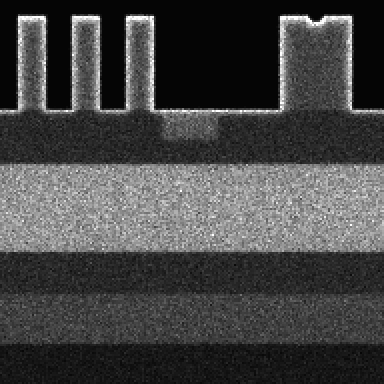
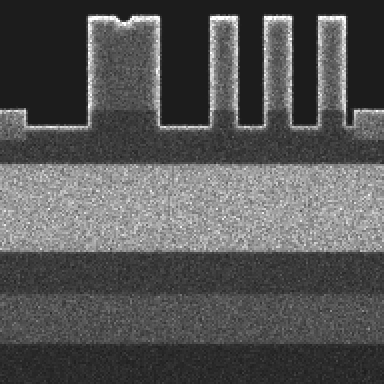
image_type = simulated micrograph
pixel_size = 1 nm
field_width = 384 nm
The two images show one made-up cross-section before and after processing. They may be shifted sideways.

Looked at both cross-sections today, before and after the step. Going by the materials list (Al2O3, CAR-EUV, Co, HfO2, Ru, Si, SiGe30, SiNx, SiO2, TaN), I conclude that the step removed SiNx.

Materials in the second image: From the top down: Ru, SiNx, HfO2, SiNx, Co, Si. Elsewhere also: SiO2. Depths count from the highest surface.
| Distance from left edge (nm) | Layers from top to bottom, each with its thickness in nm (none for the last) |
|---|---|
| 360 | empty 94, Ru 30, SiNx 24, HfO2 88, SiNx 42, Co 50, Si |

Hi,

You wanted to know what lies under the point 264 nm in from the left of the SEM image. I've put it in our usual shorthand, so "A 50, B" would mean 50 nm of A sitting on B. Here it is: SiO2 94, SiNx 54, HfO2 88, SiNx 42, Co 50, Si